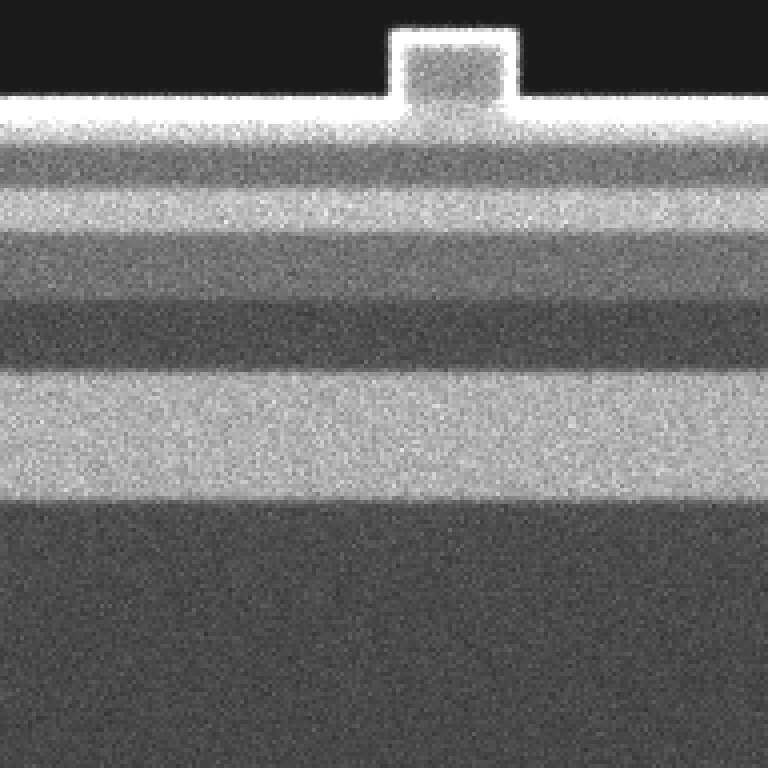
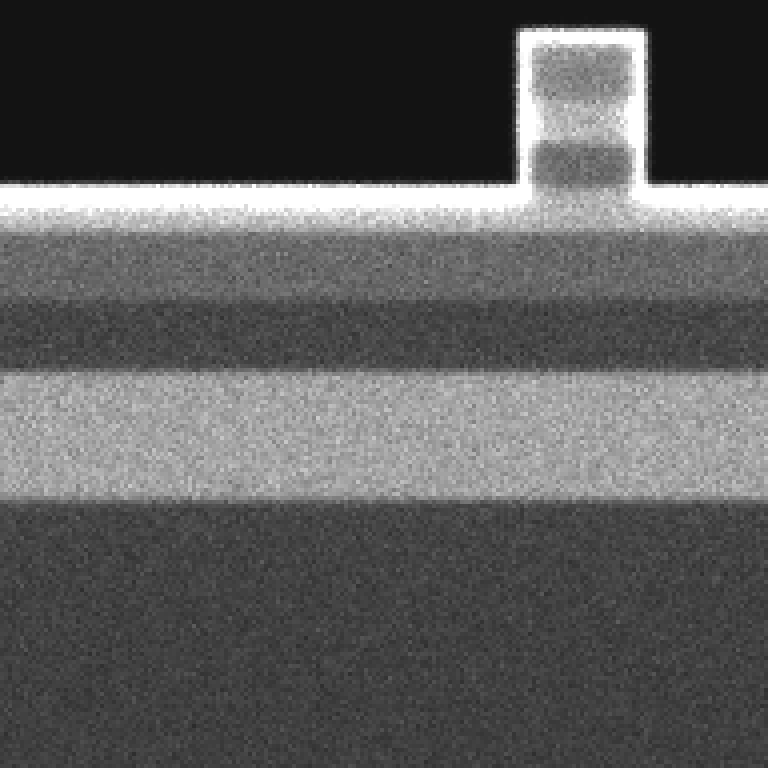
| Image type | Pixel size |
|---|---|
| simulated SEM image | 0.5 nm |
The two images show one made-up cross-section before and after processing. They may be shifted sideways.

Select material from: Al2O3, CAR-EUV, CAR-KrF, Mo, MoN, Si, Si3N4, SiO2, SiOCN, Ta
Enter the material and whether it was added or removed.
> Al2O3 and SiOCN / removed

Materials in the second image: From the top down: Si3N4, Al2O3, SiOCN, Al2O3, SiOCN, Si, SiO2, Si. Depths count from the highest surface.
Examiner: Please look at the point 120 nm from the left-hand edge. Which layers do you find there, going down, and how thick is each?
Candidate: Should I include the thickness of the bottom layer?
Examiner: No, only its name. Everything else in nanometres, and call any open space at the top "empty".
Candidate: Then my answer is empty 78, Al2O3 22, SiOCN 34, Si 36, SiO2 64, Si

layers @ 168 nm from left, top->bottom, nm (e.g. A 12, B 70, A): empty 78, Al2O3 22, SiOCN 34, Si 36, SiO2 64, Si